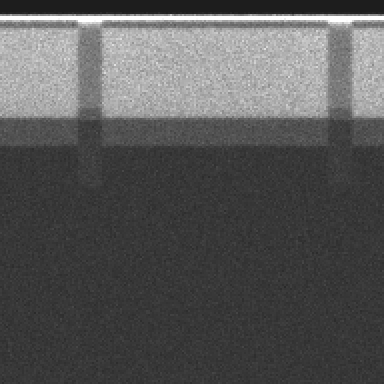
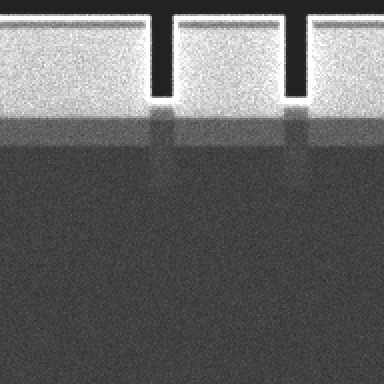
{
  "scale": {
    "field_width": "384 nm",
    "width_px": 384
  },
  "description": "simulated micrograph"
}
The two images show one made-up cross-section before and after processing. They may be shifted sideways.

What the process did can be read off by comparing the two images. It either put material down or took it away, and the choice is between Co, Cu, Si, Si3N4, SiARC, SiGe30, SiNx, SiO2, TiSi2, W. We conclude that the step removed SiO2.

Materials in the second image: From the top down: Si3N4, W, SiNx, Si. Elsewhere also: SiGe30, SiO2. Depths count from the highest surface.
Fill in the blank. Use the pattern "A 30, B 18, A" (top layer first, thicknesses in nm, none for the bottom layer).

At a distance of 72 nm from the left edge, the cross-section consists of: Si3N4 12, W 90, SiNx 28, Si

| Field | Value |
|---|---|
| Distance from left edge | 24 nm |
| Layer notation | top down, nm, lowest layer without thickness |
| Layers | Si3N4 12, W 90, SiNx 28, Si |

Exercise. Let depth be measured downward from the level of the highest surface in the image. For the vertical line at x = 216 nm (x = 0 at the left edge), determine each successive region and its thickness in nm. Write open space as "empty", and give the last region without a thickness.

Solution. Si3N4 12, W 90, SiNx 28, Si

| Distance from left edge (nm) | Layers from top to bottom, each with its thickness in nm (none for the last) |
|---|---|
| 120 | Si3N4 12, W 90, SiNx 28, Si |